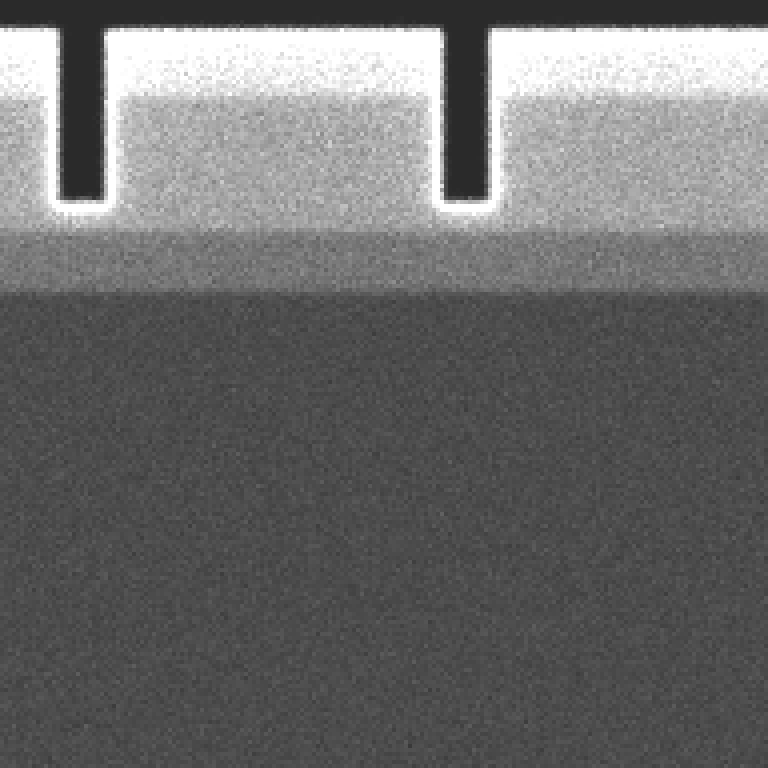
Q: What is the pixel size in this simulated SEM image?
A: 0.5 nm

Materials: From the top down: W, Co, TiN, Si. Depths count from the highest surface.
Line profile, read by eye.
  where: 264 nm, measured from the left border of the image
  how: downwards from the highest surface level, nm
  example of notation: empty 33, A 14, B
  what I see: W 32, Co 68, TiN 30, Si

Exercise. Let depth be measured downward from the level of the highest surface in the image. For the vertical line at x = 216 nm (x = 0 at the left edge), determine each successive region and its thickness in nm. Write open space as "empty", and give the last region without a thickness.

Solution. W 32, Co 68, TiN 30, Si